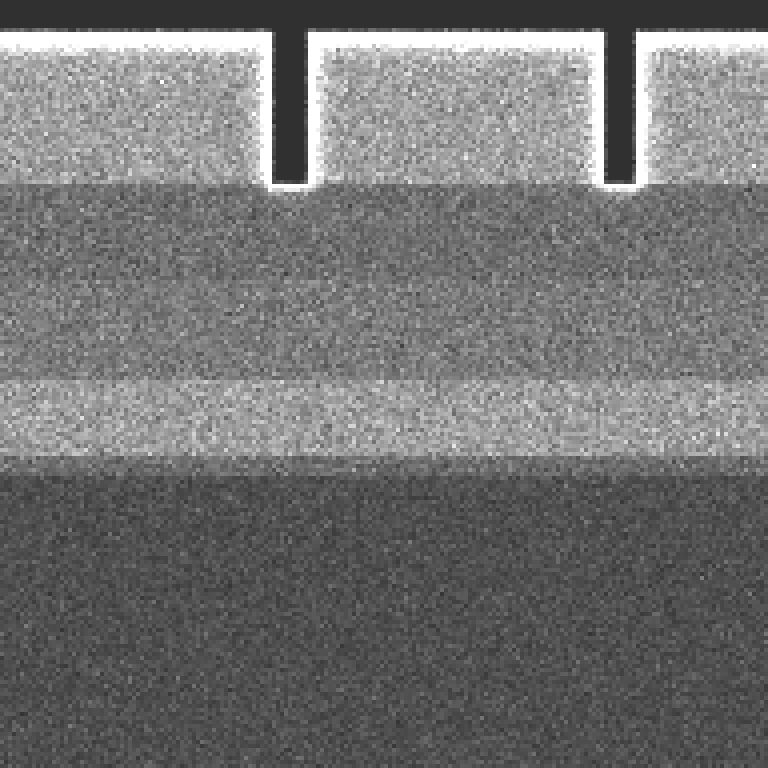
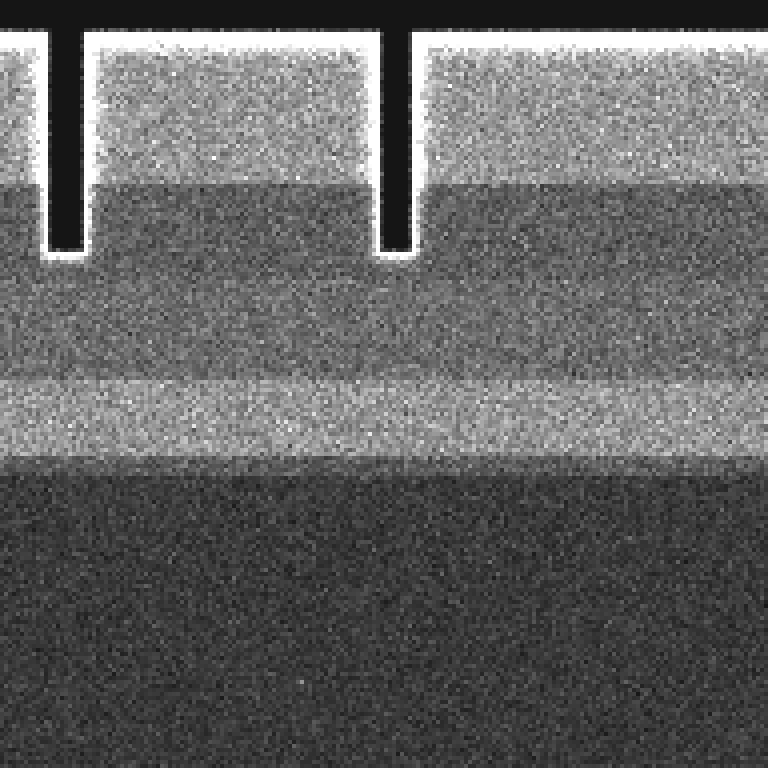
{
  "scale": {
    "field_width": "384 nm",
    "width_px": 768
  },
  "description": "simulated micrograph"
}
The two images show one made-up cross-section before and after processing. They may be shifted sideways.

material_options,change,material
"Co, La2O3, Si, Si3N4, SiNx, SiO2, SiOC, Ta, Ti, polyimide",removed,SiNx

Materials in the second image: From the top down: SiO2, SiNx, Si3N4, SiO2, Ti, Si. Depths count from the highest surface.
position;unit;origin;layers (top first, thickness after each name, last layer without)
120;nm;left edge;SiO2 76, SiNx 48, Si3N4 50, SiO2 38, Ti 10, Si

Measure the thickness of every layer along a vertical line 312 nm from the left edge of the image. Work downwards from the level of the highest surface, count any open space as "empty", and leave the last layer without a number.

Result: SiO2 76, SiNx 48, Si3N4 50, SiO2 38, Ti 10, Si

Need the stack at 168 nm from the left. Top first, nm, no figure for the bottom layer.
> SiO2 76, SiNx 48, Si3N4 50, SiO2 38, Ti 10, Si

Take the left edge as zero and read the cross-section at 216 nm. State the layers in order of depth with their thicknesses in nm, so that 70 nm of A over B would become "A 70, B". SiO2 76, SiNx 48, Si3N4 50, SiO2 38, Ti 10, Si